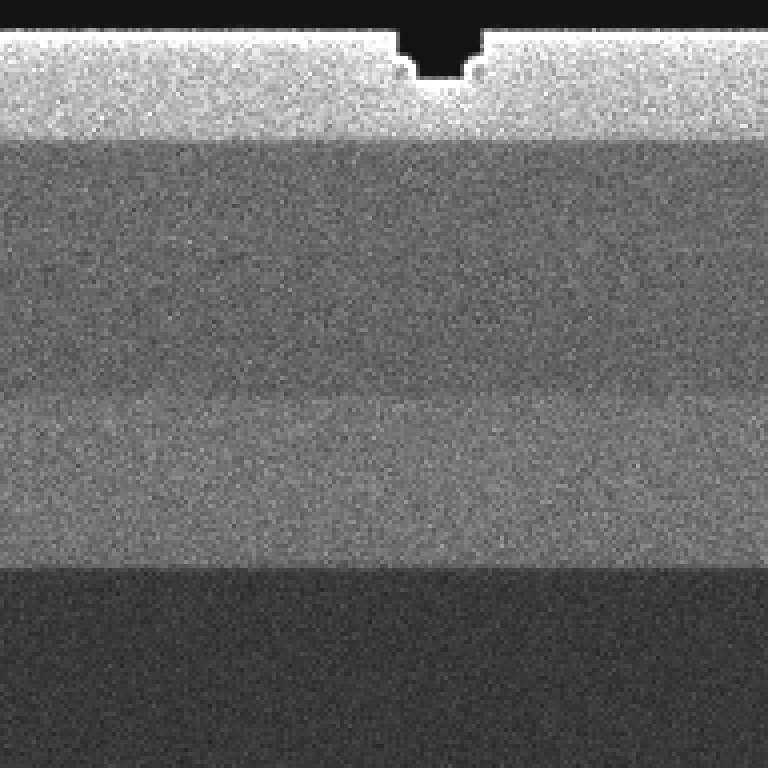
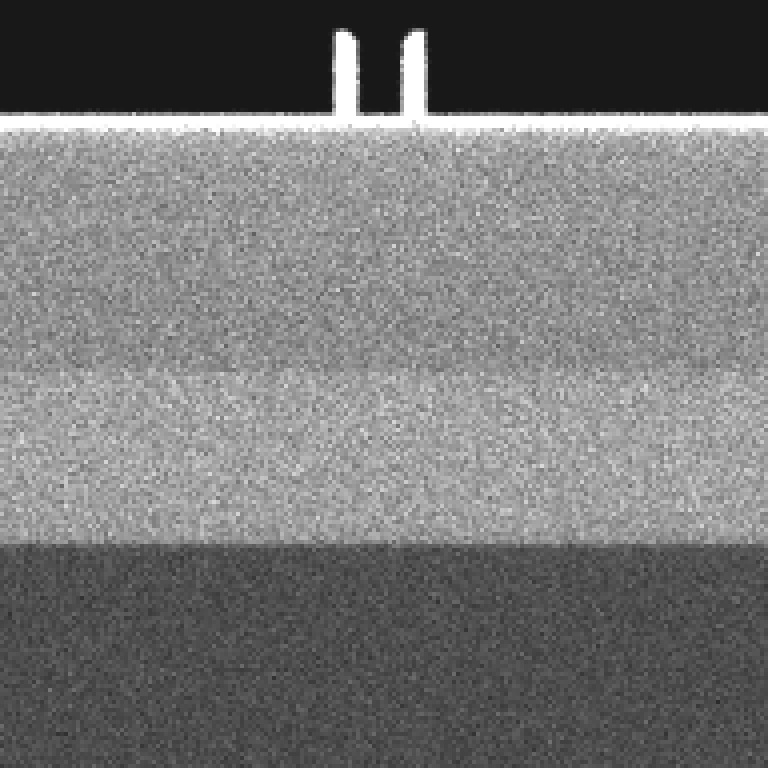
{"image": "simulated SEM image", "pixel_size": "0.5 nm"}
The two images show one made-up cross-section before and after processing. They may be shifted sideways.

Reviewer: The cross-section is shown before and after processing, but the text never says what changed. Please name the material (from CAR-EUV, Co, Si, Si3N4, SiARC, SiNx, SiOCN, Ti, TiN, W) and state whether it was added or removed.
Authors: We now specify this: Co, removed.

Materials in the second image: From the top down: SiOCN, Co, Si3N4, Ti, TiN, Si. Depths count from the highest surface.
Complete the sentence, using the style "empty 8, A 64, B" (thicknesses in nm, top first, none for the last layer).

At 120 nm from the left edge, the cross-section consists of empty 42, Si3N4 56, Ti 72, TiN 86, Si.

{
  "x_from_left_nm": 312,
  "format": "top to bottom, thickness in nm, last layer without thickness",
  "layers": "empty 42, Si3N4 56, Ti 72, TiN 86, Si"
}